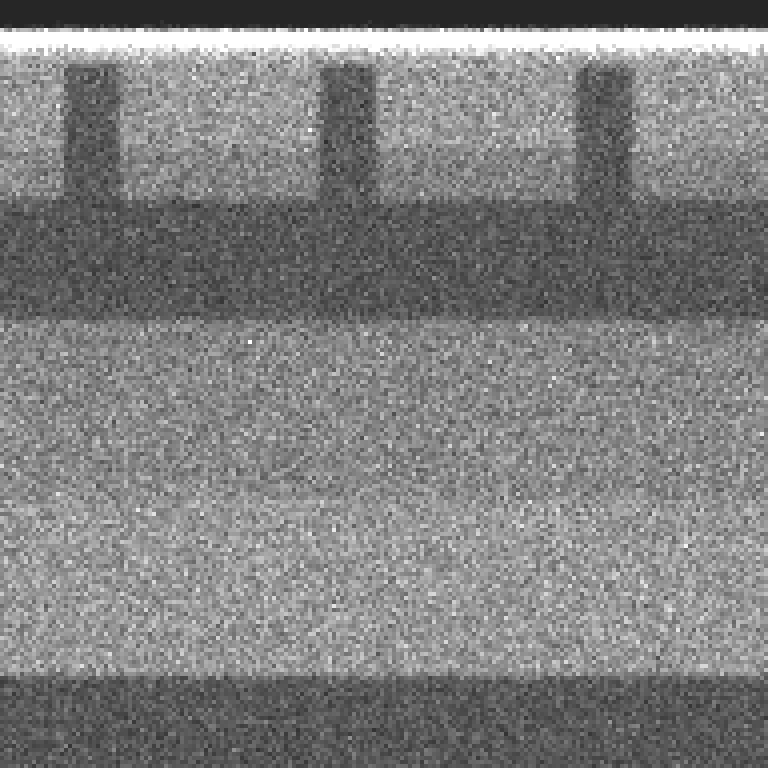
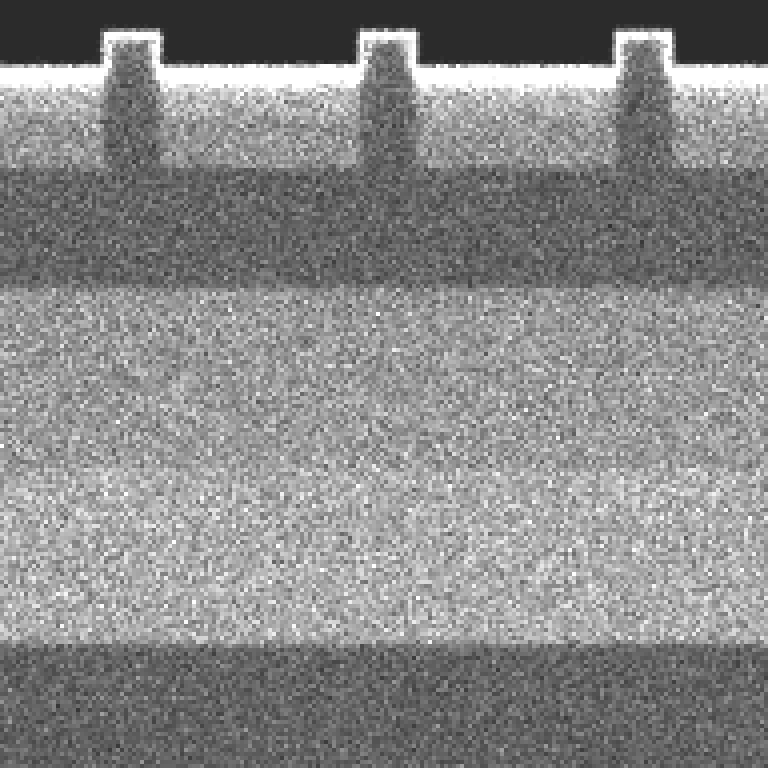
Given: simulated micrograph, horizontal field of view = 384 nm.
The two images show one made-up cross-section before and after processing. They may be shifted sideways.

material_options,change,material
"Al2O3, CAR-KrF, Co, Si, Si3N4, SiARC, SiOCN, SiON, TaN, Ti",removed,SiARC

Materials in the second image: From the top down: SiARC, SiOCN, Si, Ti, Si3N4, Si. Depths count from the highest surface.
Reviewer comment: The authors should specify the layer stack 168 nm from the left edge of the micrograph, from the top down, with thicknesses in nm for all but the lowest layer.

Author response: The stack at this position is empty 18, SiARC 24, SiOCN 26, Si 60, Ti 90, Si3N4 88, Si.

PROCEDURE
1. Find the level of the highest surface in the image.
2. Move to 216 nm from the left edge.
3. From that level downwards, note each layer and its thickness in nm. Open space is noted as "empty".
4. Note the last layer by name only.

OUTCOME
empty 18, SiARC 24, SiOCN 26, Si 60, Ti 90, Si3N4 88, Si